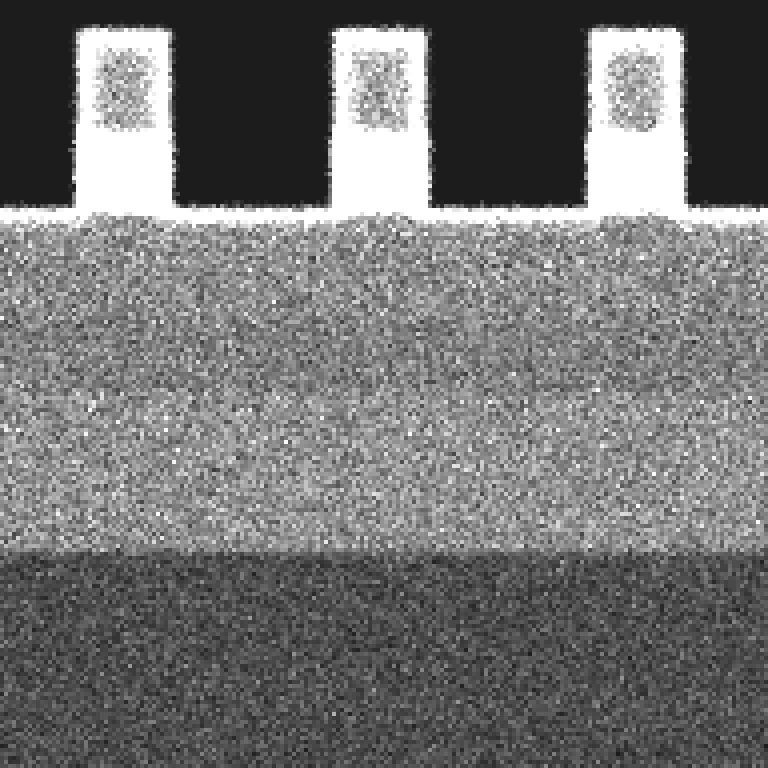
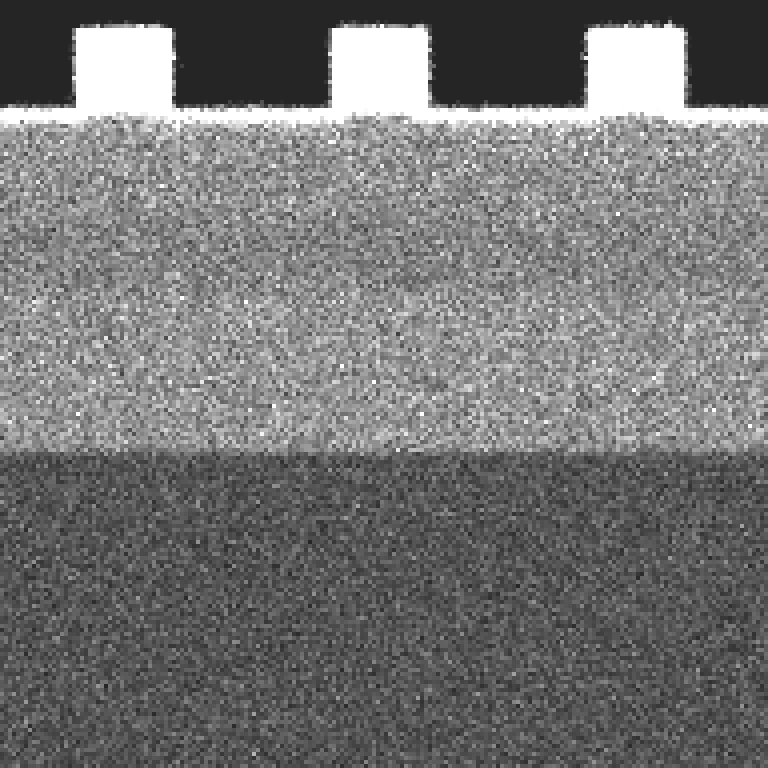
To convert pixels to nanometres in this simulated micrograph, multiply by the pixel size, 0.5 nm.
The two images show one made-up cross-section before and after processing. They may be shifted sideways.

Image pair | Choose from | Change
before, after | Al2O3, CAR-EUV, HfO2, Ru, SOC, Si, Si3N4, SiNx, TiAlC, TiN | SOC (removed)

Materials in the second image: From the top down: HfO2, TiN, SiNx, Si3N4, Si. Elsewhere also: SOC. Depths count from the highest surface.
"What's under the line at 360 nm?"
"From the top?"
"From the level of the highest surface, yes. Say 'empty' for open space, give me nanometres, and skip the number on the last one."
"empty 40, TiN 54, SiNx 36, Si3N4 80, Si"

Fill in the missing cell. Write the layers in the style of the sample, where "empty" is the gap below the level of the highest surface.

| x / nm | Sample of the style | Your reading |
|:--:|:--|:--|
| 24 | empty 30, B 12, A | empty 40, TiN 54, SiNx 36, Si3N4 80, Si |